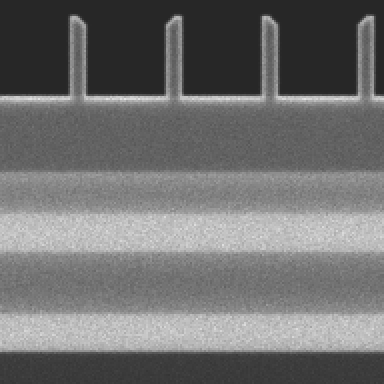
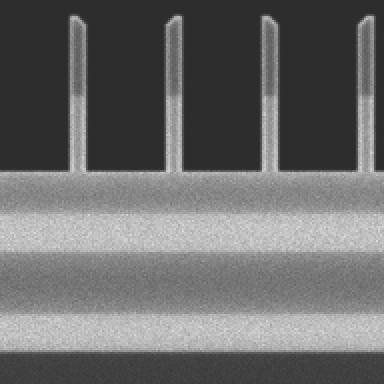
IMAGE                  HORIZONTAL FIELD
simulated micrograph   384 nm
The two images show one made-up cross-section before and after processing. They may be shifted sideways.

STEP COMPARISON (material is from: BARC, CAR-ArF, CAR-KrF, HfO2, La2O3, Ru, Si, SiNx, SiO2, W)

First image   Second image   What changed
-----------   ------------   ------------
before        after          SiO2, removed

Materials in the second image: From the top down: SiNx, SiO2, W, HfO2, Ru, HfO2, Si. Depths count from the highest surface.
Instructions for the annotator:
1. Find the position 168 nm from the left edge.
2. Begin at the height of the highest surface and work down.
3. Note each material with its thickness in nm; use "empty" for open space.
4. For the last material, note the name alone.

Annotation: empty 6, SiNx 74, SiO2 76, W 42, HfO2 38, Ru 62, HfO2 38, Si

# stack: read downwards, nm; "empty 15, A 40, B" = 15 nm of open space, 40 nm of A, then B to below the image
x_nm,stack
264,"SiNx 80, SiO2 76, W 42, HfO2 38, Ru 62, HfO2 38, Si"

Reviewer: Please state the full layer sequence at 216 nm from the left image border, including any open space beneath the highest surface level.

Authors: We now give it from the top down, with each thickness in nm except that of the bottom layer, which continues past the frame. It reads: empty 156, W 42, HfO2 38, Ru 62, HfO2 38, Si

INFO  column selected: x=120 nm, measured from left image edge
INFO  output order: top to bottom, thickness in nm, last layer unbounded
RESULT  empty 156, W 42, HfO2 38, Ru 62, HfO2 38, Si